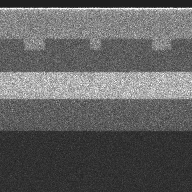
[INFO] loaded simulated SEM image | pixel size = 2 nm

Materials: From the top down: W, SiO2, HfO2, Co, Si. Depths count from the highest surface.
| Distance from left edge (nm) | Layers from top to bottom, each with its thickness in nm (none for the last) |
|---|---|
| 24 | W 62, SiO2 66, HfO2 54, Co 64, Si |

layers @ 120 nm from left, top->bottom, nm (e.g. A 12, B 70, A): W 62, SiO2 66, HfO2 54, Co 64, Si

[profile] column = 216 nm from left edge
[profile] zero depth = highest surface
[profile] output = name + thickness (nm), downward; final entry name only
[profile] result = W 62, SiO2 66, HfO2 54, Co 64, Si